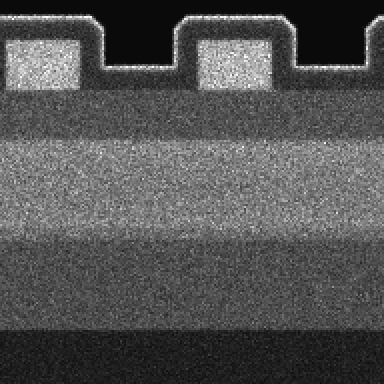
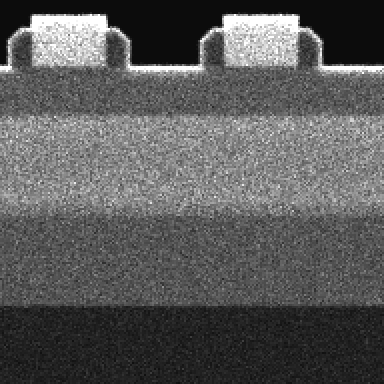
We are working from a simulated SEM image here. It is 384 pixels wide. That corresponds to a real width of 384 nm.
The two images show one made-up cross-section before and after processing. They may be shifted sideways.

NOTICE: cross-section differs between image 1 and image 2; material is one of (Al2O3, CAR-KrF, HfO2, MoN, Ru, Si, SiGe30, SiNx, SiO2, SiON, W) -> removed: SiNx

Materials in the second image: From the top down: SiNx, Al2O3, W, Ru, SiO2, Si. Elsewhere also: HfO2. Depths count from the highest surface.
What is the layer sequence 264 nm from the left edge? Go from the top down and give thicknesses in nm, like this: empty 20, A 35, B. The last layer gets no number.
HfO2 50, Al2O3 50, W 88, Ru 12, SiO2 90, Si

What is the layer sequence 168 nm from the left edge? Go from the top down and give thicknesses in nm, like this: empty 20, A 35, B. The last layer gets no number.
empty 50, Al2O3 50, W 88, Ru 12, SiO2 90, Si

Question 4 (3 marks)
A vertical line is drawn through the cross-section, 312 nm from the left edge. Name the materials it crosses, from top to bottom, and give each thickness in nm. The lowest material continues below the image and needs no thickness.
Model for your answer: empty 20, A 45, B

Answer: empty 16, SiNx 34, Al2O3 50, W 88, Ru 12, SiO2 90, Si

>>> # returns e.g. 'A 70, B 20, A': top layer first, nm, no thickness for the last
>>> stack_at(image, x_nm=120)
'empty 16, SiNx 34, Al2O3 50, W 88, Ru 12, SiO2 90, Si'